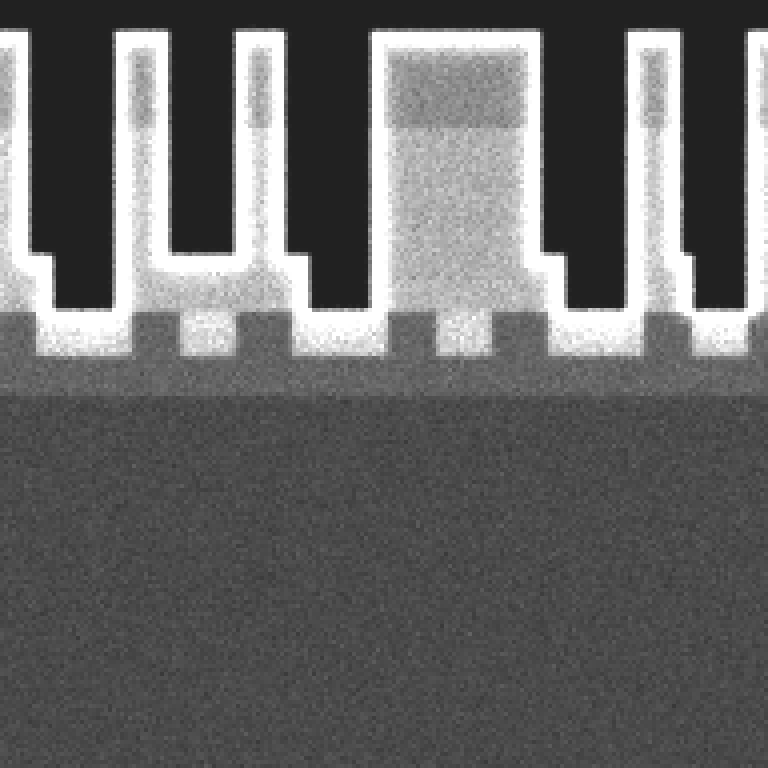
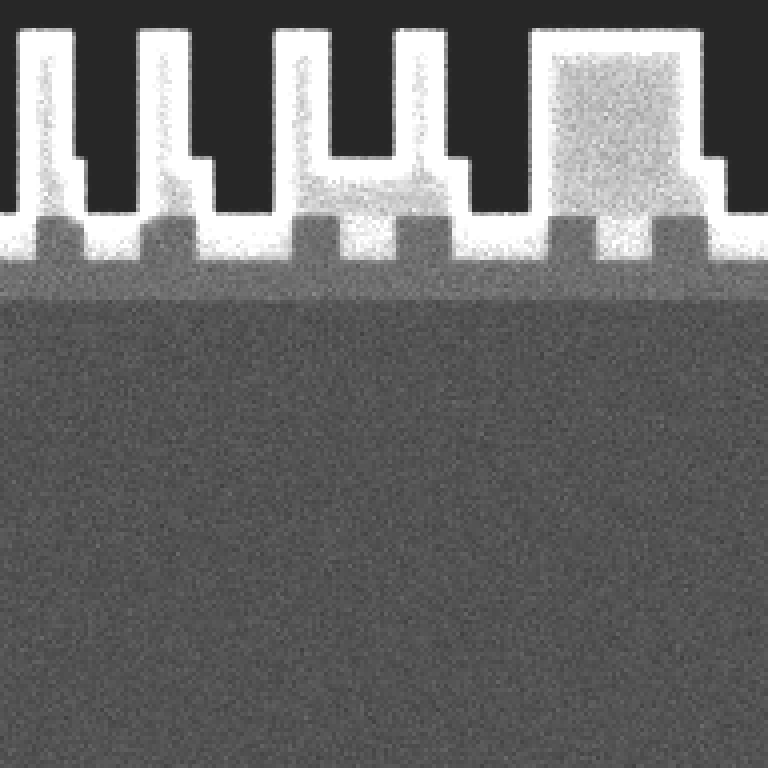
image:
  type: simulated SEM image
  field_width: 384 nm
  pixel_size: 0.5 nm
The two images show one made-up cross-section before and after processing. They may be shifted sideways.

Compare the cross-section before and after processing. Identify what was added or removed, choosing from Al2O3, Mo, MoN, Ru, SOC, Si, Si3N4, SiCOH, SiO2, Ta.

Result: SOC removed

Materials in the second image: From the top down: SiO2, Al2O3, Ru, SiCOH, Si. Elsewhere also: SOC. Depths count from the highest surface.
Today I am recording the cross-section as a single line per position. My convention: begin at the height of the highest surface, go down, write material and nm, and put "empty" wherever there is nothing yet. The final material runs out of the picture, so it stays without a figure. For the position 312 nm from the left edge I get SiO2 76, Al2O3 16, Ru 22, SiCOH 20, Si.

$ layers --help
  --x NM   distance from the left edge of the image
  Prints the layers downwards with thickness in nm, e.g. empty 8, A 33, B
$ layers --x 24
SiO2 76, Al2O3 16, SiCOH 42, Si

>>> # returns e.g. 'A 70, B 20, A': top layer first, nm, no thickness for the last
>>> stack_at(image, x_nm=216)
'SiO2 76, Al2O3 16, SiCOH 42, Si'